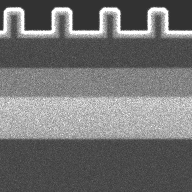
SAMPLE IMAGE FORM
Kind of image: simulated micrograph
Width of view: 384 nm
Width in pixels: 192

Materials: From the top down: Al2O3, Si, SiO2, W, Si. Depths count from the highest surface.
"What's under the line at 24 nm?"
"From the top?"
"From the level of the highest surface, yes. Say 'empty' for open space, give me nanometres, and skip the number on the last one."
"Al2O3 14, Si 106, SiO2 58, W 84, Si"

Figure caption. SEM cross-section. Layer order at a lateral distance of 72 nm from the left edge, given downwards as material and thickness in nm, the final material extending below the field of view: empty 46, Al2O3 14, Si 60, SiO2 58, W 84, Si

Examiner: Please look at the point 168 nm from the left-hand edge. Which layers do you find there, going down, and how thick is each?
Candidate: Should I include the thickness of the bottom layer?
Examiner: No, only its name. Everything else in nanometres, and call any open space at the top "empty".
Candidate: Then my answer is empty 46, Al2O3 14, Si 60, SiO2 58, W 84, Si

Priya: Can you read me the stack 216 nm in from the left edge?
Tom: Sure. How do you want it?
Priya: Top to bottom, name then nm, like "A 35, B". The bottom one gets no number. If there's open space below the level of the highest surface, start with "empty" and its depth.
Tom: Al2O3 14, Si 106, SiO2 58, W 84, Si